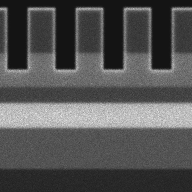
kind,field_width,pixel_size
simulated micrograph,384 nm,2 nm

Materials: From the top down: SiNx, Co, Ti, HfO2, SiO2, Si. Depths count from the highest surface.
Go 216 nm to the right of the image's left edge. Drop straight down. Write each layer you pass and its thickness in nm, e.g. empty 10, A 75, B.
empty 124, Co 34, Ti 32, HfO2 50, SiO2 82, Si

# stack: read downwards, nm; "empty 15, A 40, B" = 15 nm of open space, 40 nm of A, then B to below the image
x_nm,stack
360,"SiNx 90, Co 68, Ti 32, HfO2 50, SiO2 82, Si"